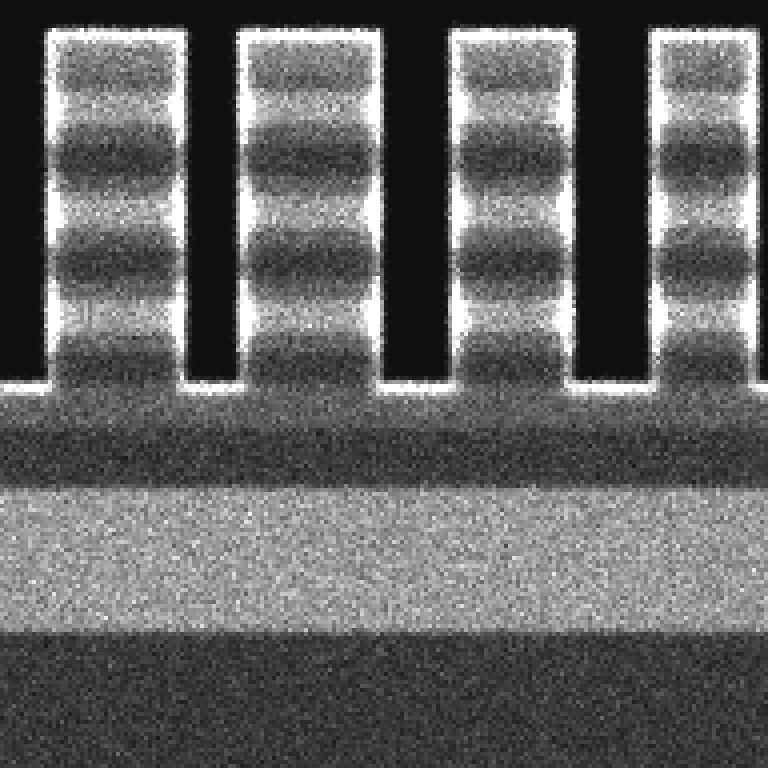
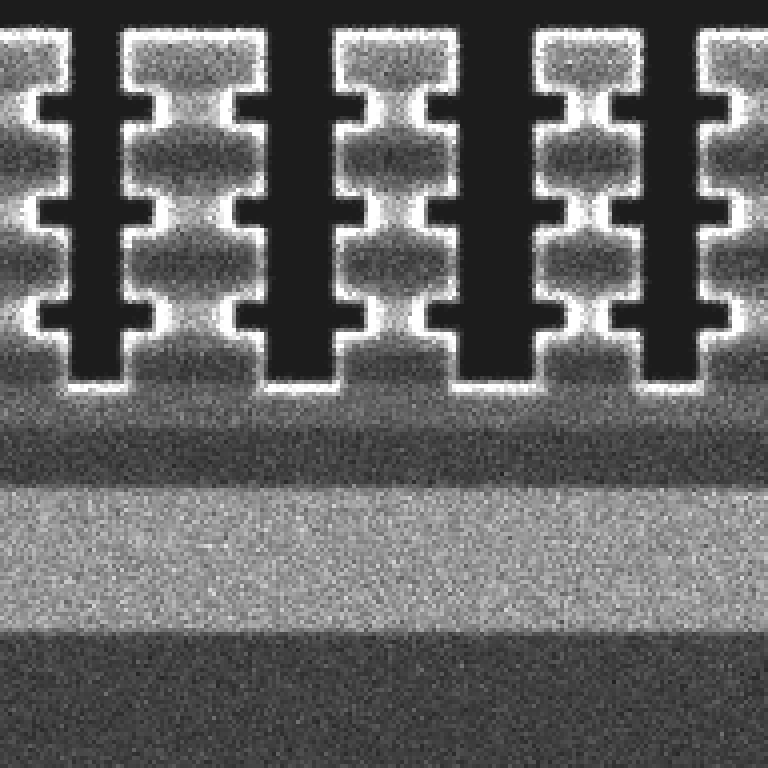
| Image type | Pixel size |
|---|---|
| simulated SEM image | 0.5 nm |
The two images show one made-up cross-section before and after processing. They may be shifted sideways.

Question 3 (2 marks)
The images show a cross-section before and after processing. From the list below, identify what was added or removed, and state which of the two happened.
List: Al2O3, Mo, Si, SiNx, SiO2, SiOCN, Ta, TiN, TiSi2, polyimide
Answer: Al2O3 was removed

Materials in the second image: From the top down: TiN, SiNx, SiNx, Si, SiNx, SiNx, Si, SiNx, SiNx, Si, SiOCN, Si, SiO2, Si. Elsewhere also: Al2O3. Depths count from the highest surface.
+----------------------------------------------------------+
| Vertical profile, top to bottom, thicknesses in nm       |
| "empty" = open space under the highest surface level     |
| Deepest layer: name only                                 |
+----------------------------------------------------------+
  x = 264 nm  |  empty 176, SiOCN 22, Si 30, SiO2 72, Si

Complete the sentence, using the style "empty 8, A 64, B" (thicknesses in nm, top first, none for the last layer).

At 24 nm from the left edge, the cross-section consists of TiN 20, SiNx 10, empty 16, SiNx 10, Si 16, SiNx 10, empty 16, SiNx 10, Si 16, SiNx 10, empty 16, SiNx 10, Si 16, SiOCN 22, Si 30, SiO2 72, Si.